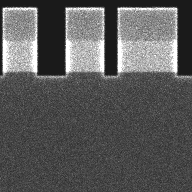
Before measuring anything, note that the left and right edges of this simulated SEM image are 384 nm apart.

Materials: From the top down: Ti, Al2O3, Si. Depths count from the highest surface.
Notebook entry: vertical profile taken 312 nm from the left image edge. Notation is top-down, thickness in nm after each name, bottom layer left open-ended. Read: Ti 66, Al2O3 62, Si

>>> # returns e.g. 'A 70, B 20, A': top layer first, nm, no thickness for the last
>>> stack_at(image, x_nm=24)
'Ti 66, Al2O3 62, Si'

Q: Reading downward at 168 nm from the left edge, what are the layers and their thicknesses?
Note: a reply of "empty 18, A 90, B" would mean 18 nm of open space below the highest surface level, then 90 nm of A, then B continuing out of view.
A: Ti 66, Al2O3 62, Si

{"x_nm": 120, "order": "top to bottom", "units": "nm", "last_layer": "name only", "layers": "empty 136, Si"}